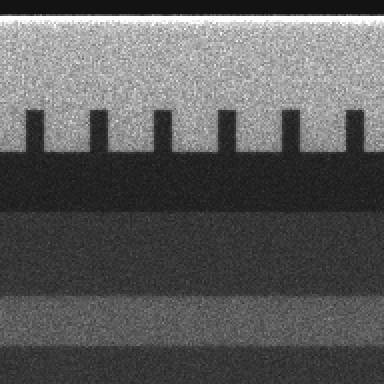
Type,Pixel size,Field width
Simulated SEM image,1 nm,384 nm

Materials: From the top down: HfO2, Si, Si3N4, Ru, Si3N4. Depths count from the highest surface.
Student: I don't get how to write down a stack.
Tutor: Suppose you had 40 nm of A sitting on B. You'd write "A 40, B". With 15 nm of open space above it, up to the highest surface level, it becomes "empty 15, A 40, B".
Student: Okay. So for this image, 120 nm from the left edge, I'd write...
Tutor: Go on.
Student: HfO2 136, Si 60, Si3N4 84, Ru 50, Si3N4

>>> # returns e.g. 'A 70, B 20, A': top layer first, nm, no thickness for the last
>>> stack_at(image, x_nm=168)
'HfO2 94, Si 102, Si3N4 84, Ru 50, Si3N4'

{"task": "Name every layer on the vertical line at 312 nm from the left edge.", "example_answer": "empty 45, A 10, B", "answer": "HfO2 136, Si 60, Si3N4 84, Ru 50, Si3N4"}